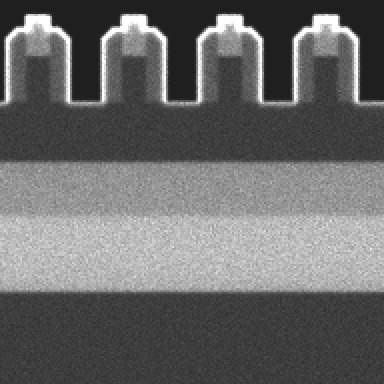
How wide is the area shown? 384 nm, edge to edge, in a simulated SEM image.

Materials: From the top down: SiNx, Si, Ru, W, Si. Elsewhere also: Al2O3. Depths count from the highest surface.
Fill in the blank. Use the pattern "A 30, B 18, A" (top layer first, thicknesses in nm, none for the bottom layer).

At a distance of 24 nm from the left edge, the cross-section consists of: empty 12, SiNx 74, Si 60, Ru 54, W 76, Si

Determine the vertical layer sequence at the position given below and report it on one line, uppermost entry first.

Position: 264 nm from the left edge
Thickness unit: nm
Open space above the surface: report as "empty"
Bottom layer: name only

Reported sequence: empty 86, Si 60, Ru 54, W 76, Si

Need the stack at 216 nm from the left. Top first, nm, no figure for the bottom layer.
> empty 12, SiNx 74, Si 60, Ru 54, W 76, Si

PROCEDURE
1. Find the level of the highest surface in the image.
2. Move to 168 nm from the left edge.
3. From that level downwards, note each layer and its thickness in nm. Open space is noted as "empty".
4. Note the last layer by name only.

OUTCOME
empty 86, Si 60, Ru 54, W 76, Si